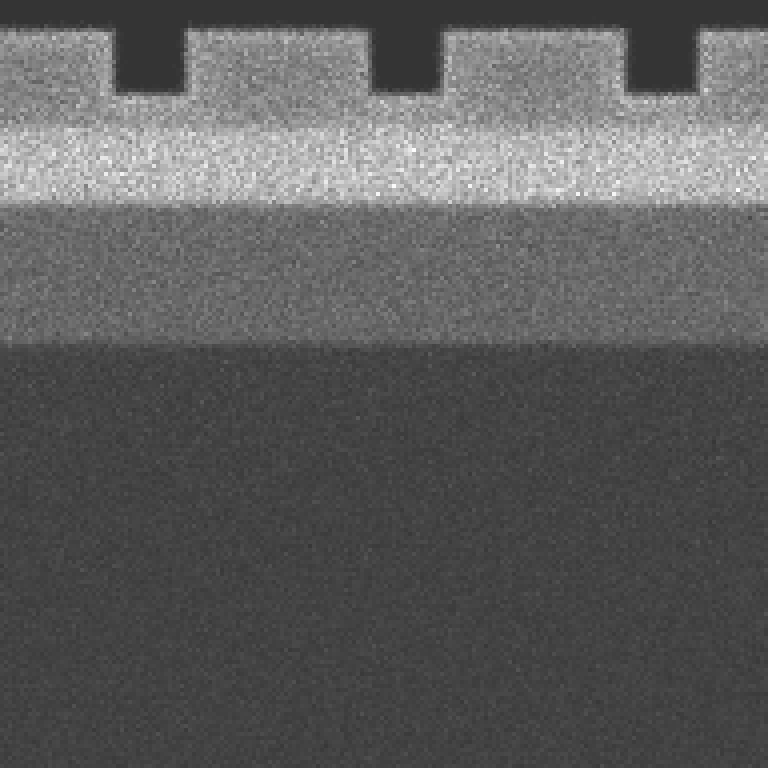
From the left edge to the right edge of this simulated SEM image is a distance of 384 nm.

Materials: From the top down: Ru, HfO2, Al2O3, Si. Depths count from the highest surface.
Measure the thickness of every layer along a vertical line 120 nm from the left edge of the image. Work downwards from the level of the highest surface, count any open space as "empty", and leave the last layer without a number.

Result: Ru 48, HfO2 38, Al2O3 70, Si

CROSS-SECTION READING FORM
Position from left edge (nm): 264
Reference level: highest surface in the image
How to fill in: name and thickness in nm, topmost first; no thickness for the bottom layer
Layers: Ru 48, HfO2 38, Al2O3 70, Si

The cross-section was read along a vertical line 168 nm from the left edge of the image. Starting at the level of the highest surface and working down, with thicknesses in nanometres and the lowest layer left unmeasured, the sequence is Ru 48, HfO2 38, Al2O3 70, Si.